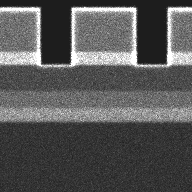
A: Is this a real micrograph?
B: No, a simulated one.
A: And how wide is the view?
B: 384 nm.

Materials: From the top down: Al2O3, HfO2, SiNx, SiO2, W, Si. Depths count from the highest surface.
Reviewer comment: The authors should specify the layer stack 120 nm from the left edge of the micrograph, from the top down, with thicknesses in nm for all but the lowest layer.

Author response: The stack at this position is empty 114, SiNx 52, SiO2 34, W 28, Si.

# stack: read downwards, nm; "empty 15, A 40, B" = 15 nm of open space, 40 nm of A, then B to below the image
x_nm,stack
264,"Al2O3 88, HfO2 26, SiNx 52, SiO2 34, W 28, Si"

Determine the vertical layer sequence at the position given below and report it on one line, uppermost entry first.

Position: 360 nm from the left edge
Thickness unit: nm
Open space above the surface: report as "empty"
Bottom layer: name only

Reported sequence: Al2O3 88, HfO2 26, SiNx 52, SiO2 34, W 28, Si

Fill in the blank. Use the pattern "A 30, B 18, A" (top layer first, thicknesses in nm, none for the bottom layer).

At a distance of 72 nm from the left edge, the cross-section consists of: Al2O3 88, HfO2 26, SiNx 52, SiO2 34, W 28, Si